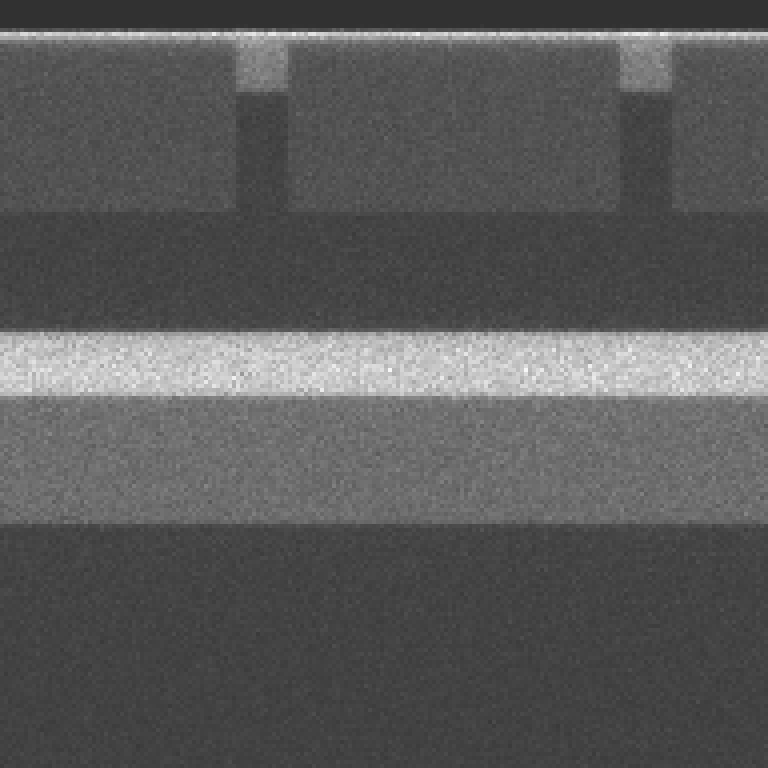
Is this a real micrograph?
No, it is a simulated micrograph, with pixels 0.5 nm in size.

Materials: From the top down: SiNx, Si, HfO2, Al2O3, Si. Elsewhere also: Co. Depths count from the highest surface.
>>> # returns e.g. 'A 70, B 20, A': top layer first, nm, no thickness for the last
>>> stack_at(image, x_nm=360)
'SiNx 90, Si 60, HfO2 32, Al2O3 64, Si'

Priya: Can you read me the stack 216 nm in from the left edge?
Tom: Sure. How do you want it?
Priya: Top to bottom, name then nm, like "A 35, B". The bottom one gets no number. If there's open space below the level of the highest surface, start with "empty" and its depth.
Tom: SiNx 90, Si 60, HfO2 32, Al2O3 64, Si